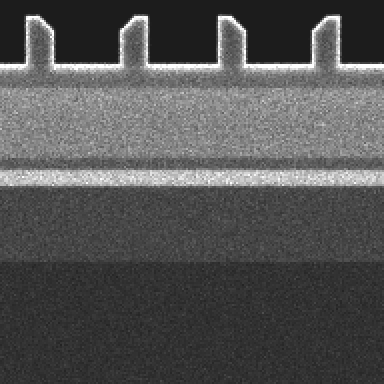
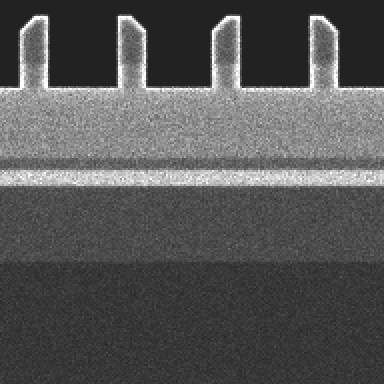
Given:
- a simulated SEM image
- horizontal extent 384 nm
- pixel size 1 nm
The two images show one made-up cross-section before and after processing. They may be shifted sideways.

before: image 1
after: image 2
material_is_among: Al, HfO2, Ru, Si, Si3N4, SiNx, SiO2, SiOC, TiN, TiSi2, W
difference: SiO2, removed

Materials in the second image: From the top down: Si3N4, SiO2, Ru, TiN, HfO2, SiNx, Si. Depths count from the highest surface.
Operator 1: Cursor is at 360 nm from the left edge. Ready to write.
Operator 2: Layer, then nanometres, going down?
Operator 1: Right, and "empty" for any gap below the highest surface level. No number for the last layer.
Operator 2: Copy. empty 72, Ru 70, TiN 12, HfO2 16, SiNx 76, Si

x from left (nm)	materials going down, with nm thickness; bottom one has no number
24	empty 10, Si3N4 38, SiO2 24, Ru 70, TiN 12, HfO2 16, SiNx 76, Si